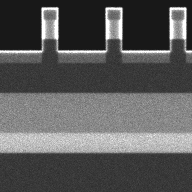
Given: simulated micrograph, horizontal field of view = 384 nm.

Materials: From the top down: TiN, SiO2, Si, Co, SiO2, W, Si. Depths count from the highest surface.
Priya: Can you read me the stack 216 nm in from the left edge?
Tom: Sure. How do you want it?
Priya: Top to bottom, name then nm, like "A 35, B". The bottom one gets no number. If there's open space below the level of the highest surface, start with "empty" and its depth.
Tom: TiN 24, SiO2 38, Si 108, Co 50, SiO2 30, W 40, Si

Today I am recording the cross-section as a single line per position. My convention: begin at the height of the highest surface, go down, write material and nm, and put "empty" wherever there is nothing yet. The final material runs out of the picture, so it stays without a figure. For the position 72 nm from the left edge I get empty 86, TiN 24, Si 60, Co 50, SiO2 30, W 40, Si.